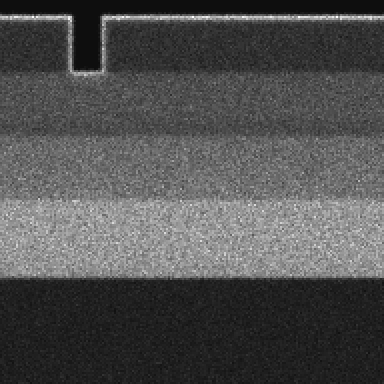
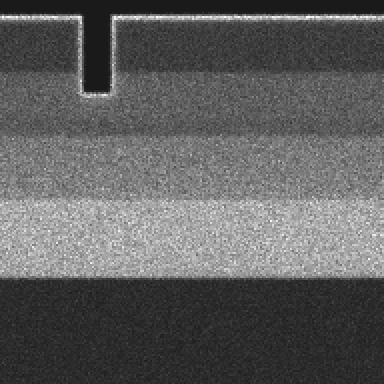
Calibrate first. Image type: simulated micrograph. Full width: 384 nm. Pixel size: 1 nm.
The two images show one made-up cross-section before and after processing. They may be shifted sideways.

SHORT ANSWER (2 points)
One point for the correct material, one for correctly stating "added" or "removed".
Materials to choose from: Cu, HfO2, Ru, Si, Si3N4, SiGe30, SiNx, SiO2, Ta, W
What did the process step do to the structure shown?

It removed Ru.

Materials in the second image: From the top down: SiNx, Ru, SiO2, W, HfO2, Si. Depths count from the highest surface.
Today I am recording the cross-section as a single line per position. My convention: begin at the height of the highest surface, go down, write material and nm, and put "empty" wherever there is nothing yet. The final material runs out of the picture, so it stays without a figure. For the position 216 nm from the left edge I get SiNx 56, Ru 48, SiO2 16, W 64, HfO2 78, Si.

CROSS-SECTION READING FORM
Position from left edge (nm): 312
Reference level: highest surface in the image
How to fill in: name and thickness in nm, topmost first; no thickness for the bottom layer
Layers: SiNx 56, Ru 48, SiO2 16, W 64, HfO2 78, Si